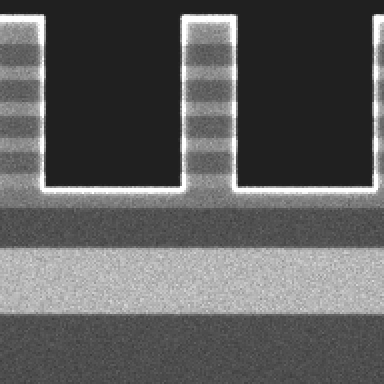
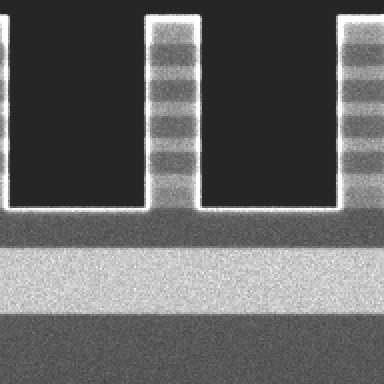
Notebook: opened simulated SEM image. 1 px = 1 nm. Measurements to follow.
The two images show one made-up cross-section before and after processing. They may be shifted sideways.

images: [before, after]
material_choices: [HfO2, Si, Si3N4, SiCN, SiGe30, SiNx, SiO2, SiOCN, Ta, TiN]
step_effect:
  removed: SiNx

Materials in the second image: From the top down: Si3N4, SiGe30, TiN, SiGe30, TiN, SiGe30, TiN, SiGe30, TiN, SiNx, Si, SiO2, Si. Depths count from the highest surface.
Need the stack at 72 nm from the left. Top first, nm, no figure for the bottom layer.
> empty 192, Si 40, SiO2 66, Si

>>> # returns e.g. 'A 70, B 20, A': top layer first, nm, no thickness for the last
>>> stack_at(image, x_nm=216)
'empty 192, Si 40, SiO2 66, Si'